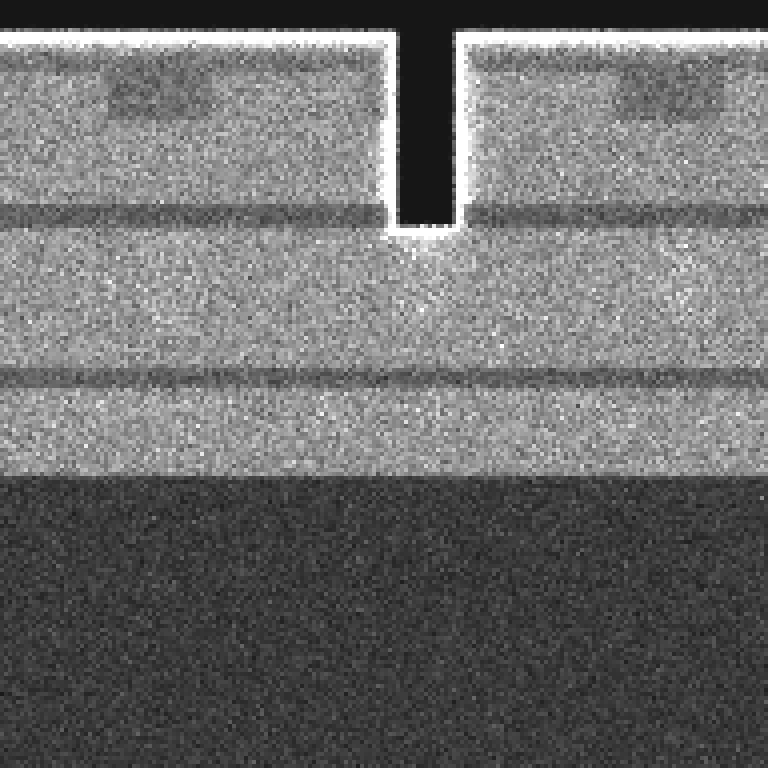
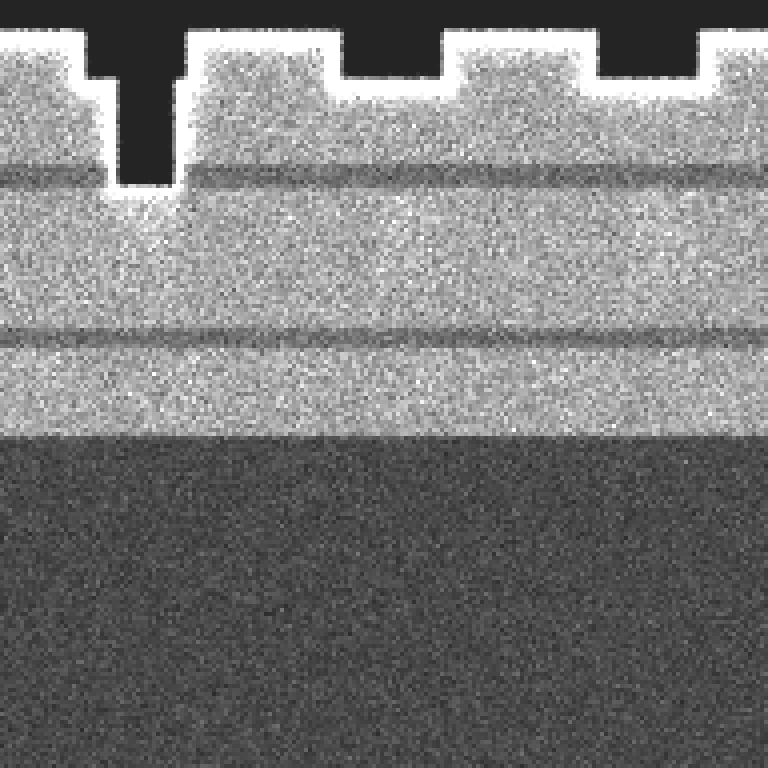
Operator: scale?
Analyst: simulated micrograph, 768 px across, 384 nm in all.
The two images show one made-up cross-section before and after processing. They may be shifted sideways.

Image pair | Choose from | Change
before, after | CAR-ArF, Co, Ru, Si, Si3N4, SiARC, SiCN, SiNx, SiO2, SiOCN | SiARC (removed)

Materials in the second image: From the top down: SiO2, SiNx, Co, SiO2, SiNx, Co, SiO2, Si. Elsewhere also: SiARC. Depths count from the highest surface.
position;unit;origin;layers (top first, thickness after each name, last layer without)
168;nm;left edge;SiO2 66, SiNx 12, SiO2 70, SiNx 10, SiO2 44, Si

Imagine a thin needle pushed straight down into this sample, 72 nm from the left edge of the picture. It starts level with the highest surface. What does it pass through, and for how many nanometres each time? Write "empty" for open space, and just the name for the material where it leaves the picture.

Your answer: empty 78, Co 48, SiO2 22, SiNx 10, SiO2 44, Si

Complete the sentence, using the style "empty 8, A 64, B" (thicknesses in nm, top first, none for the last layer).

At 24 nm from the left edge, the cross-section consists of SiO2 66, SiNx 12, SiO2 70, SiNx 10, Co 20, SiO2 24, Si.